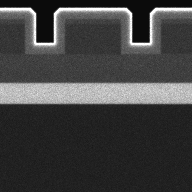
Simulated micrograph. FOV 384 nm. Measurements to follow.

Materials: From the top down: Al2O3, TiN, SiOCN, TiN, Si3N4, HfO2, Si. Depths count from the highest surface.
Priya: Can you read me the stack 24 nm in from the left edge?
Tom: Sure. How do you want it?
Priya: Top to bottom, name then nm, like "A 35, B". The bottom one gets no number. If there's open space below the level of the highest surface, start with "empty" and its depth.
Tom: Al2O3 22, TiN 10, SiOCN 60, TiN 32, Si3N4 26, HfO2 42, Si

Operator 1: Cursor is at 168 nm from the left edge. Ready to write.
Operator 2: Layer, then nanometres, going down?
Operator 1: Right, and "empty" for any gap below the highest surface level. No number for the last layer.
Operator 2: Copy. Al2O3 22, TiN 10, SiOCN 60, TiN 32, Si3N4 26, HfO2 42, Si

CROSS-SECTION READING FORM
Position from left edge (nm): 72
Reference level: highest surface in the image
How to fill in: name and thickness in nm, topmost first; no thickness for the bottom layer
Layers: empty 70, Al2O3 22, TiN 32, Si3N4 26, HfO2 42, Si